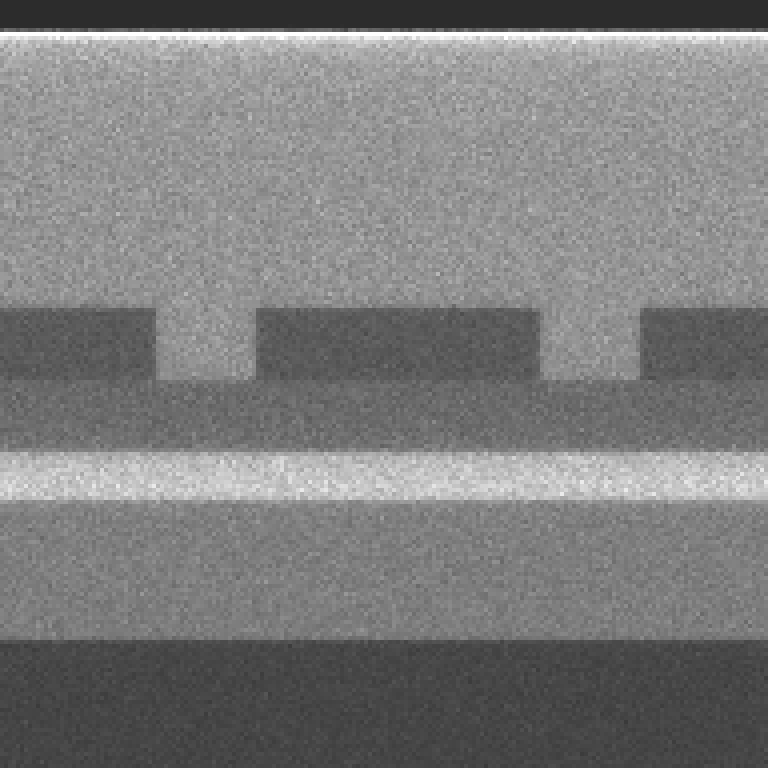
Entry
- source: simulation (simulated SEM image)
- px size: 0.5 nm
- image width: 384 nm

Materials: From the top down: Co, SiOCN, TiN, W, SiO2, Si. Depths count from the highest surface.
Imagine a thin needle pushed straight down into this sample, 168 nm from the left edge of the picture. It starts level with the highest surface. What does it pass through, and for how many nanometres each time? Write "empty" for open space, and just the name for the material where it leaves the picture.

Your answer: Co 138, SiOCN 36, TiN 36, W 24, SiO2 70, Si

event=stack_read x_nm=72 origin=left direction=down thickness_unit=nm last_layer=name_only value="Co 138, SiOCN 36, TiN 36, W 24, SiO2 70, Si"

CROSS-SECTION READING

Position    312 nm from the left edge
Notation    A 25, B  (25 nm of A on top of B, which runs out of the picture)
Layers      Co 174, TiN 36, W 24, SiO2 70, Si